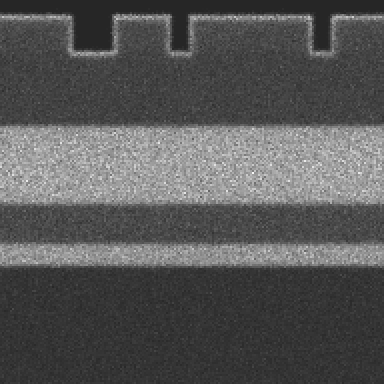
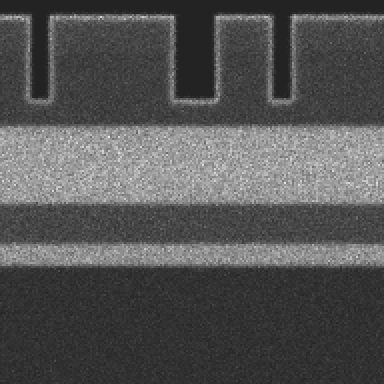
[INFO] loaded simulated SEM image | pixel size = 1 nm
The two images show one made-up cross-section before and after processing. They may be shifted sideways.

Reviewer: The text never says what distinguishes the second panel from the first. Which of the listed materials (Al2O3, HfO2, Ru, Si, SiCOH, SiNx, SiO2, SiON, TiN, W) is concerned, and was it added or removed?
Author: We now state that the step removed SiNx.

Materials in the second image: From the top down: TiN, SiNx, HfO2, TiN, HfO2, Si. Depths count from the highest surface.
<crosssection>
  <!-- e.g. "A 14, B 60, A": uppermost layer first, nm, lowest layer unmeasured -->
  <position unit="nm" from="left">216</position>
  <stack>TiN 36, SiNx 74, HfO2 78, TiN 40, HfO2 22, Si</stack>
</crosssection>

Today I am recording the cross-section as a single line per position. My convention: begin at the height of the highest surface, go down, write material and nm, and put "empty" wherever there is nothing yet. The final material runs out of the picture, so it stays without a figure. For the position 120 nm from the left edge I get TiN 36, SiNx 74, HfO2 78, TiN 40, HfO2 22, Si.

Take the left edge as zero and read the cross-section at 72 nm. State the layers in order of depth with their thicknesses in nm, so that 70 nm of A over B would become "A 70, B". TiN 36, SiNx 74, HfO2 78, TiN 40, HfO2 22, Si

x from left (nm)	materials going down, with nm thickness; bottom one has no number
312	TiN 36, SiNx 74, HfO2 78, TiN 40, HfO2 22, Si